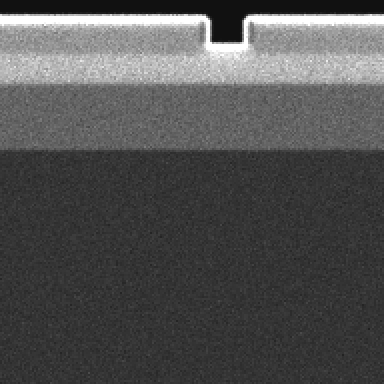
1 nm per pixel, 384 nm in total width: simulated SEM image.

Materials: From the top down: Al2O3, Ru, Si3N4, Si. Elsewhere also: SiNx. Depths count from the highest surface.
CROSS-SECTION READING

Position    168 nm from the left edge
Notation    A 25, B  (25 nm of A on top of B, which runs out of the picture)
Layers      Al2O3 38, Ru 30, Si3N4 66, Si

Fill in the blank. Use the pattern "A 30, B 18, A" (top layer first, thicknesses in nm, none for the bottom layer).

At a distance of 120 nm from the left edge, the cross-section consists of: Al2O3 38, Ru 30, Si3N4 66, Si